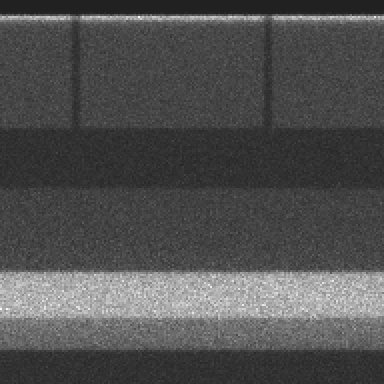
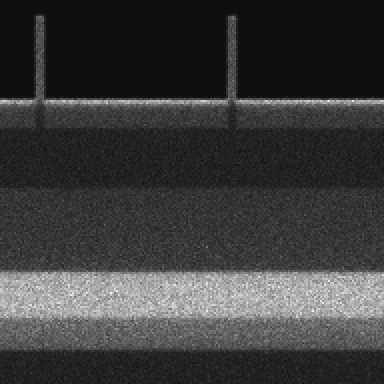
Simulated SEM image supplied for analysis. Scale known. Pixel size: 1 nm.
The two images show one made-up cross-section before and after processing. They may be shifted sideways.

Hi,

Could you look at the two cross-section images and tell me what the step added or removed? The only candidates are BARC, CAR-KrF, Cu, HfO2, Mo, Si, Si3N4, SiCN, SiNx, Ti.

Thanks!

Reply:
removed Si3N4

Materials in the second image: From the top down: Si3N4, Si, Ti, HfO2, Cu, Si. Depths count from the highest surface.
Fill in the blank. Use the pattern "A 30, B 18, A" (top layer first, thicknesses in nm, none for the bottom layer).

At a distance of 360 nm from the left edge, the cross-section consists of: empty 84, Si3N4 28, Si 60, Ti 84, HfO2 46, Cu 32, Si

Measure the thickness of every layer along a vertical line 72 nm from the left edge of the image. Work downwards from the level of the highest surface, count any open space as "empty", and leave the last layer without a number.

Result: empty 84, Si3N4 28, Si 60, Ti 84, HfO2 46, Cu 32, Si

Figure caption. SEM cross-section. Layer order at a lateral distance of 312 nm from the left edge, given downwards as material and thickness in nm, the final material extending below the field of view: empty 84, Si3N4 28, Si 60, Ti 84, HfO2 46, Cu 32, Si